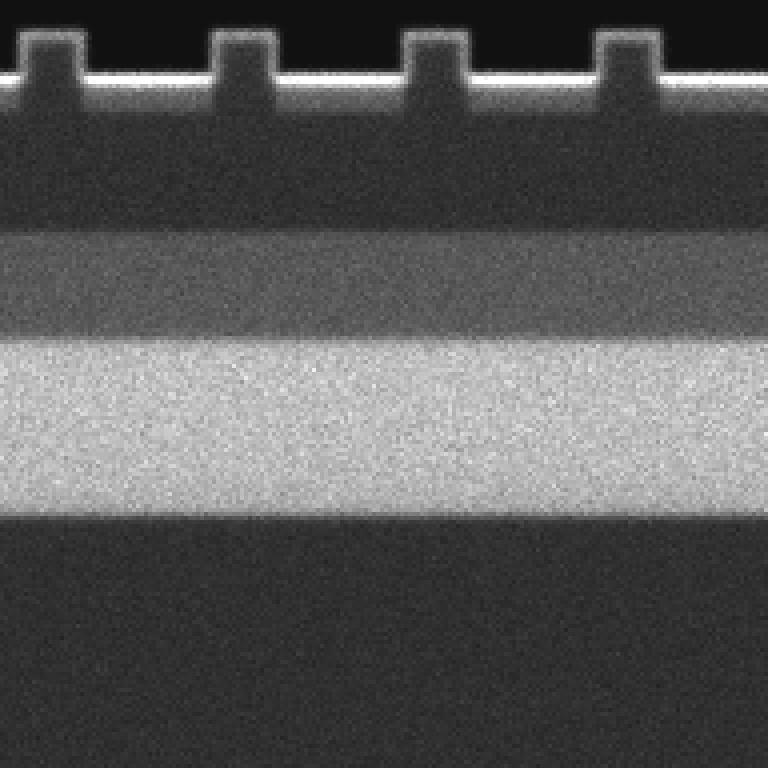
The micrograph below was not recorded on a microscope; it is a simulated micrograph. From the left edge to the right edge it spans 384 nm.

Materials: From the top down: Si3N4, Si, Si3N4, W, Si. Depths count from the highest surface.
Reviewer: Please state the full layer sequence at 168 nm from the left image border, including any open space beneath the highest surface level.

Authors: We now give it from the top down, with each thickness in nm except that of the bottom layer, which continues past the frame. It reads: empty 22, Si3N4 18, Si 60, Si3N4 54, W 88, Si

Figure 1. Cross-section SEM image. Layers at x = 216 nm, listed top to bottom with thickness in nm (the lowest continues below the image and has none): Si 100, Si3N4 54, W 88, Si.